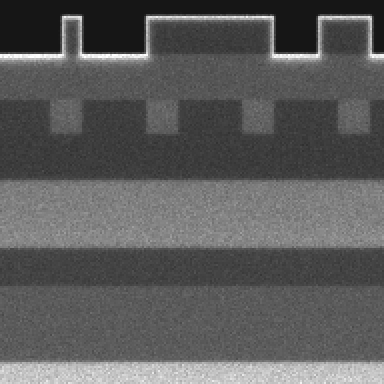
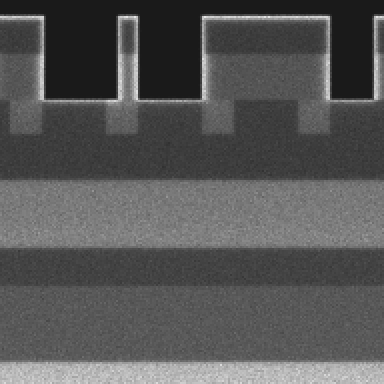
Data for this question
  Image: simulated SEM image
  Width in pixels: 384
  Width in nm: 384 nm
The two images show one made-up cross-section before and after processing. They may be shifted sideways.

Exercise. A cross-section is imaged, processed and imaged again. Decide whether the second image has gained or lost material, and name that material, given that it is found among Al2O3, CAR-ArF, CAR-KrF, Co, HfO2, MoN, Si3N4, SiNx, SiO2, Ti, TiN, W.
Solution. removed: SiO2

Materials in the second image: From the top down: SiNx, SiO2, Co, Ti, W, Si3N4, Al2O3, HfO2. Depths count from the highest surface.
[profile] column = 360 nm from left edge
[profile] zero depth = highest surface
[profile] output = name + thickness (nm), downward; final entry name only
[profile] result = empty 84, Ti 80, W 68, Si3N4 38, Al2O3 76, HfO2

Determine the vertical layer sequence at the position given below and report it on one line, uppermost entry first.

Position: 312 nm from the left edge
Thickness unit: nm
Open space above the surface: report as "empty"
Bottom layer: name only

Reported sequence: SiNx 38, SiO2 46, Co 34, Ti 46, W 68, Si3N4 38, Al2O3 76, HfO2